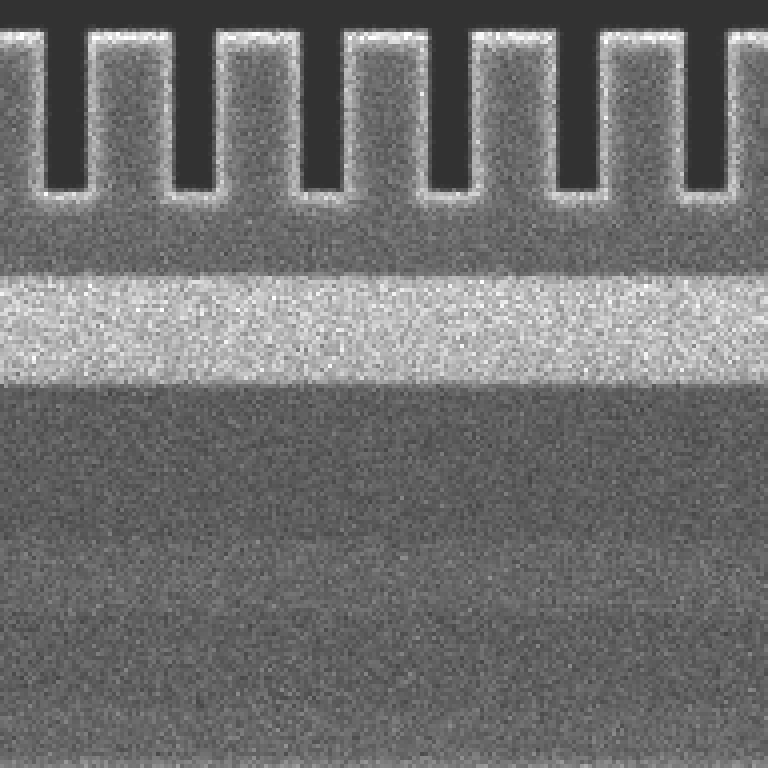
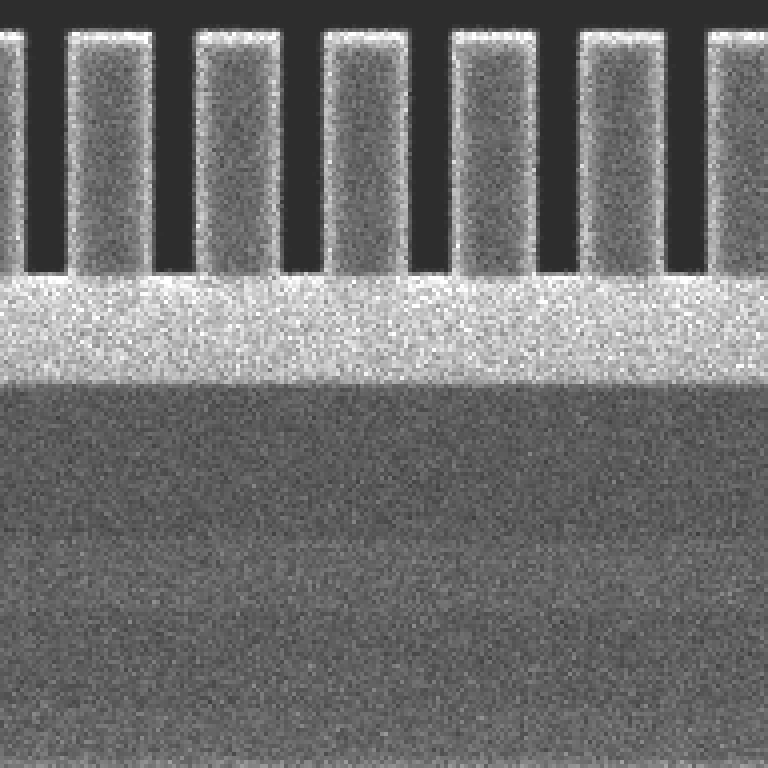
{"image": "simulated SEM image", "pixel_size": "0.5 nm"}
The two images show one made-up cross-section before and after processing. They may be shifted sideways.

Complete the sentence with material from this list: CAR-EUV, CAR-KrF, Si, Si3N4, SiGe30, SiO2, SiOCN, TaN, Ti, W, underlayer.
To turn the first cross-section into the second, underlayer must be removed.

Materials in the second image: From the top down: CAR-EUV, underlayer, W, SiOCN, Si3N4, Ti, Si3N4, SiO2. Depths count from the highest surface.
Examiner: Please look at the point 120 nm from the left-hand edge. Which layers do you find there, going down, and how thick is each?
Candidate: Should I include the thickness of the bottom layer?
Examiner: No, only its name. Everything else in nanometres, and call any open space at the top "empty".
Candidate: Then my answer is CAR-EUV 80, underlayer 42, W 54, SiOCN 78, Si3N4 36, Ti 48, Si3N4 26, SiO2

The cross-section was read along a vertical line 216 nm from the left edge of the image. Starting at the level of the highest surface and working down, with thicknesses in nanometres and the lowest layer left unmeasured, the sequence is empty 122, W 54, SiOCN 78, Si3N4 36, Ti 48, Si3N4 26, SiO2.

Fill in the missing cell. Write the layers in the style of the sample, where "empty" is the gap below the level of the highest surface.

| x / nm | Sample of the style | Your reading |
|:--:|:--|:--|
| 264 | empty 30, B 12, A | CAR-EUV 80, underlayer 42, W 54, SiOCN 78, Si3N4 36, Ti 48, Si3N4 26, SiO2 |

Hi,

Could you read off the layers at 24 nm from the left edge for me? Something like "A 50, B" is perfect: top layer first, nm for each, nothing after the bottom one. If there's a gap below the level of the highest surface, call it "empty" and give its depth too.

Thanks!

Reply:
empty 122, W 54, SiOCN 78, Si3N4 36, Ti 48, Si3N4 26, SiO2